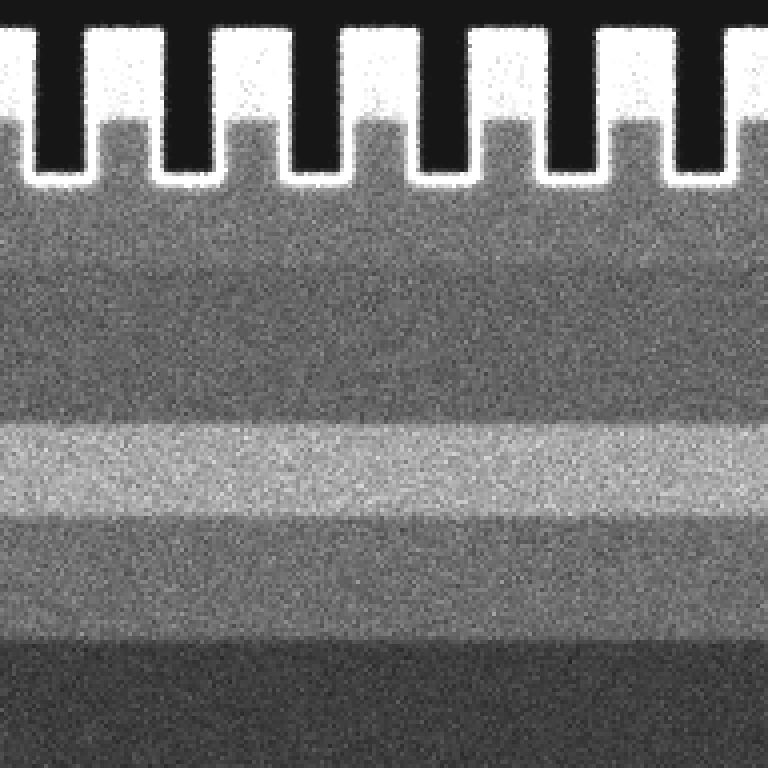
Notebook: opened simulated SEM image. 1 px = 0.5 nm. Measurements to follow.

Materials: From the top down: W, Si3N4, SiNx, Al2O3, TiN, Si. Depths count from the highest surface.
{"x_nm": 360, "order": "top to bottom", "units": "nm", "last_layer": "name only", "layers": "empty 72, Si3N4 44, SiNx 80, Al2O3 46, TiN 62, Si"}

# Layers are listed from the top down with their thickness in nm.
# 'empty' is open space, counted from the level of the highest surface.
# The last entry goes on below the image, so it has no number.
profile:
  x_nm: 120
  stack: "W 44, Si3N4 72, SiNx 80, Al2O3 46, TiN 62, Si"